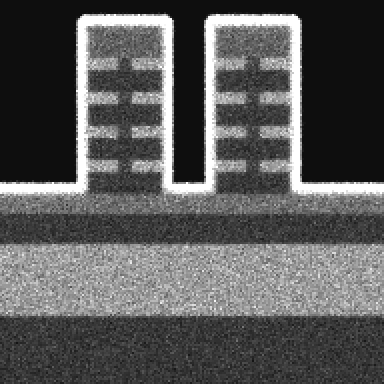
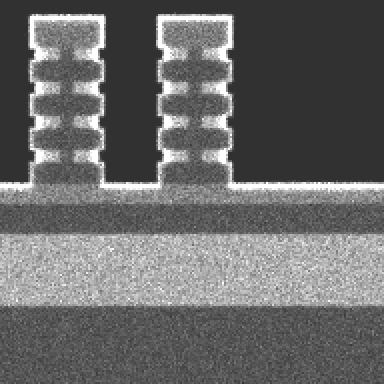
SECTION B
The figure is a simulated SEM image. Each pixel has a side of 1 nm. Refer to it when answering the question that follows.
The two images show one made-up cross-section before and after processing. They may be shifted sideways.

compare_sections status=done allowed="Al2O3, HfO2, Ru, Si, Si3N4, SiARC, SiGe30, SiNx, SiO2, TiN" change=removed material="Al2O3"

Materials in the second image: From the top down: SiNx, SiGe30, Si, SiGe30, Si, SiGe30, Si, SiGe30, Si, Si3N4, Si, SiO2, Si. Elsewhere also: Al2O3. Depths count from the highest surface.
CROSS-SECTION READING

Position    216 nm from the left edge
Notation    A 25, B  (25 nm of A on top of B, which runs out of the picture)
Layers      SiNx 32, Al2O3 12, Si 22, Al2O3 12, Si 22, Al2O3 12, Si 22, Al2O3 12, Si 22, Si3N4 20, Si 30, SiO2 72, Si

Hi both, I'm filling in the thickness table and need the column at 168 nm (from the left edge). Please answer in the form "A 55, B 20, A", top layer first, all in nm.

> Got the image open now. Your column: SiNx 32, Al2O3 12, Si 22, Al2O3 12, Si 22, Al2O3 12, Si 22, Al2O3 12, Si 22, Si3N4 20, Si 30, SiO2 72, Si